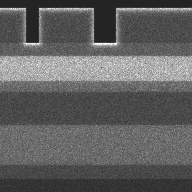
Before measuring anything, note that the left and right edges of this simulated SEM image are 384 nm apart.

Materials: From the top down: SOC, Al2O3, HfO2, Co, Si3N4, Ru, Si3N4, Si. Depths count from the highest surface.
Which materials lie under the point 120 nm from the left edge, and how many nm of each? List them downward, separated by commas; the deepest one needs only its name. SOC 70, Al2O3 26, HfO2 50, Co 22, Si3N4 66, Ru 80, Si3N4 28, Si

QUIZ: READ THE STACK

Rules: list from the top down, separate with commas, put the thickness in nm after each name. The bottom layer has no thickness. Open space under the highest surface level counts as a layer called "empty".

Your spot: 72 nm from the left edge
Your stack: empty 70, Al2O3 26, HfO2 50, Co 22, Si3N4 66, Ru 80, Si3N4 28, Si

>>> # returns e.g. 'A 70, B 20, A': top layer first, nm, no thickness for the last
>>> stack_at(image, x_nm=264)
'SOC 70, Al2O3 26, HfO2 50, Co 22, Si3N4 66, Ru 80, Si3N4 28, Si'